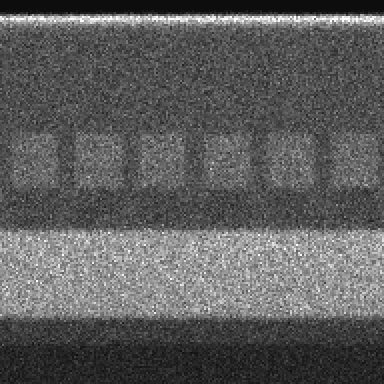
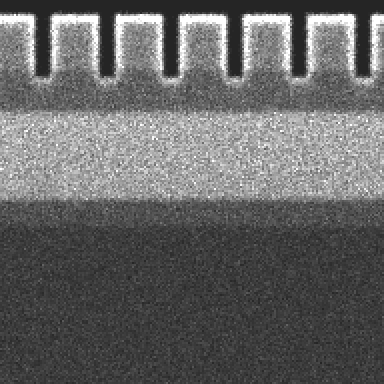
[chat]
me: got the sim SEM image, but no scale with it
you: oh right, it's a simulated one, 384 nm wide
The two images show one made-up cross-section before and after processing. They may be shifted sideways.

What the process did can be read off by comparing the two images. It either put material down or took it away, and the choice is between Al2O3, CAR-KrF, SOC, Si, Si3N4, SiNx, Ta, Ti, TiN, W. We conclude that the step removed SOC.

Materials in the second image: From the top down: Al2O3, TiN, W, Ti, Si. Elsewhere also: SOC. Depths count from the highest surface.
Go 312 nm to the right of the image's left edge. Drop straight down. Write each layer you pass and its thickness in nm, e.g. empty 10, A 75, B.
Al2O3 54, TiN 42, W 88, Ti 26, Si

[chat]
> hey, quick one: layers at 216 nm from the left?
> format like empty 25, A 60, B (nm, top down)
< Al2O3 54, TiN 42, W 88, Ti 26, Si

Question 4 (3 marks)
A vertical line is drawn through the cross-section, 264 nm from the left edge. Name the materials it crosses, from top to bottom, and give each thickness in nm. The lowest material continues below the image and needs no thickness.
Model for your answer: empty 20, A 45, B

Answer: Al2O3 54, TiN 42, W 88, Ti 26, Si